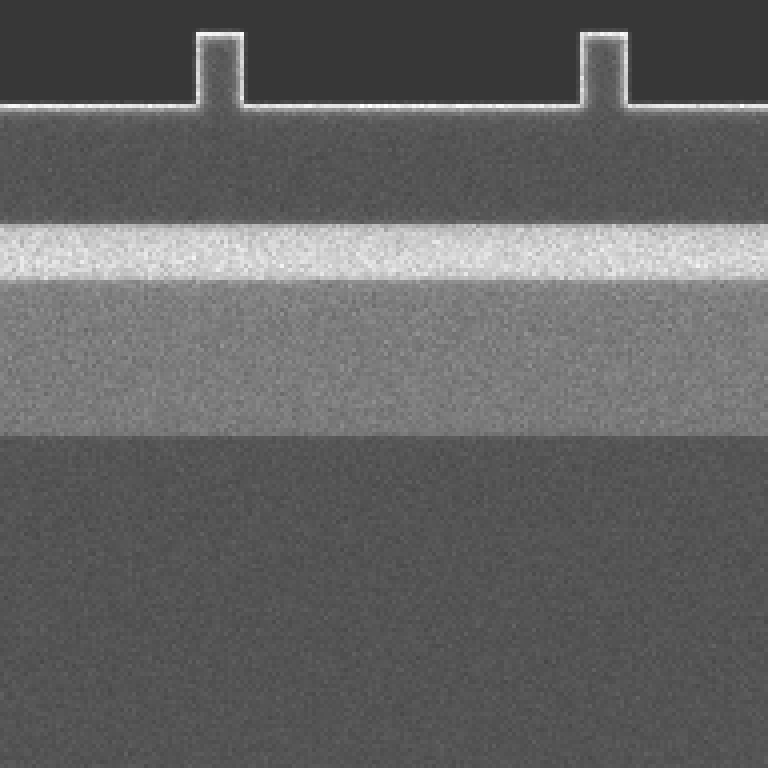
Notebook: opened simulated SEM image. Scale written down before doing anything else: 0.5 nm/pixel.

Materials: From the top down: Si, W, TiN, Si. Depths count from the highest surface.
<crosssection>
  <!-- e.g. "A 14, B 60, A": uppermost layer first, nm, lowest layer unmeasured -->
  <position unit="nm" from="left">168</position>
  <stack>empty 36, Si 60, W 28, TiN 78, Si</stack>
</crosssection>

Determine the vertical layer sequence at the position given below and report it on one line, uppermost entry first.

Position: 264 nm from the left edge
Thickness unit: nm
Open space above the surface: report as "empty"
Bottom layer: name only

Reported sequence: empty 36, Si 60, W 28, TiN 78, Si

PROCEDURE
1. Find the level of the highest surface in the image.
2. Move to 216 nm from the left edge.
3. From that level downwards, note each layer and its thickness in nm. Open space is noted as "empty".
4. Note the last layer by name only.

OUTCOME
empty 36, Si 60, W 28, TiN 78, Si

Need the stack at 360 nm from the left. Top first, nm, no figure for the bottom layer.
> empty 36, Si 60, W 28, TiN 78, Si